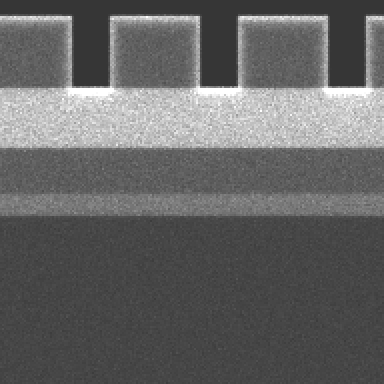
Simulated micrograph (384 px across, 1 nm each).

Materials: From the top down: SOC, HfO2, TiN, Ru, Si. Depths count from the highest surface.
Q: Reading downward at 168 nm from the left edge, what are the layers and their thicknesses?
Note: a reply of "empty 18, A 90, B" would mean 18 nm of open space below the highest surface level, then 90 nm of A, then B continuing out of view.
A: SOC 72, HfO2 60, TiN 46, Ru 22, Si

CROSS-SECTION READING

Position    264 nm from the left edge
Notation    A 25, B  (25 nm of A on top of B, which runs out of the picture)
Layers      SOC 72, HfO2 60, TiN 46, Ru 22, Si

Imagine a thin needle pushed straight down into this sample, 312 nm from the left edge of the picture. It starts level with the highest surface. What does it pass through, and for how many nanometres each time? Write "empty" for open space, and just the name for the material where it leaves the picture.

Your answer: SOC 72, HfO2 60, TiN 46, Ru 22, Si